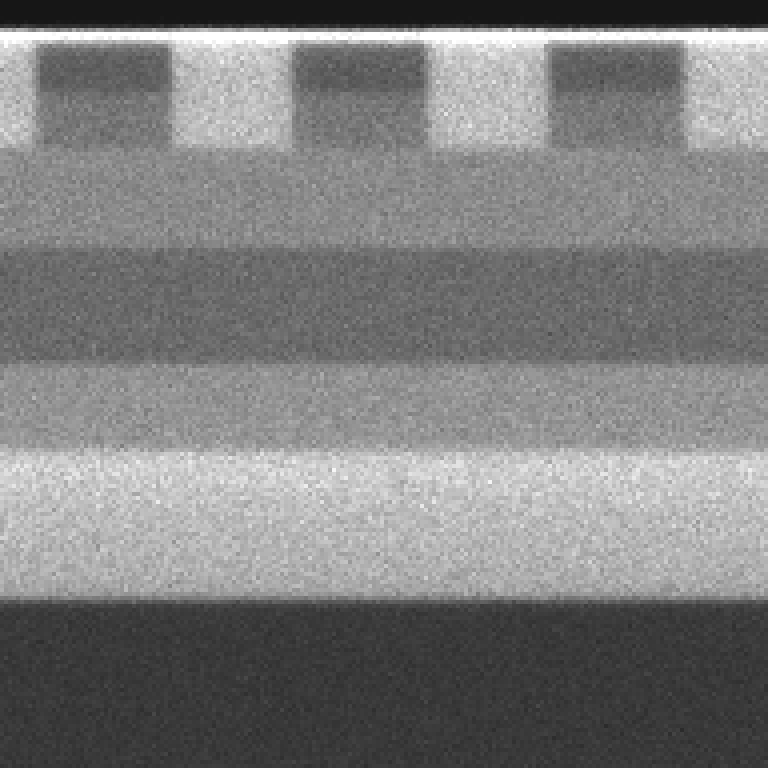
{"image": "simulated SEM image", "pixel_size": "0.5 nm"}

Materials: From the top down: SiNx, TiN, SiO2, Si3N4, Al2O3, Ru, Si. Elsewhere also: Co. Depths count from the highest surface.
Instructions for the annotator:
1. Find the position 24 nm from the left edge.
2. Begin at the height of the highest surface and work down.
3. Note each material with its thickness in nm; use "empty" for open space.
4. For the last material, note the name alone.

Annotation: SiNx 30, TiN 28, SiO2 50, Si3N4 58, Al2O3 44, Ru 74, Si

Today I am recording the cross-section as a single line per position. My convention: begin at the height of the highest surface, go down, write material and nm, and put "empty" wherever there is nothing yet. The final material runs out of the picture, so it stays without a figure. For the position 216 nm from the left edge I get Co 58, SiO2 50, Si3N4 58, Al2O3 44, Ru 74, Si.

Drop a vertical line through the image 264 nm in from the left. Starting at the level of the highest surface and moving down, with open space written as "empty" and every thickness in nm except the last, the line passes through Co 58, SiO2 50, Si3N4 58, Al2O3 44, Ru 74, Si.